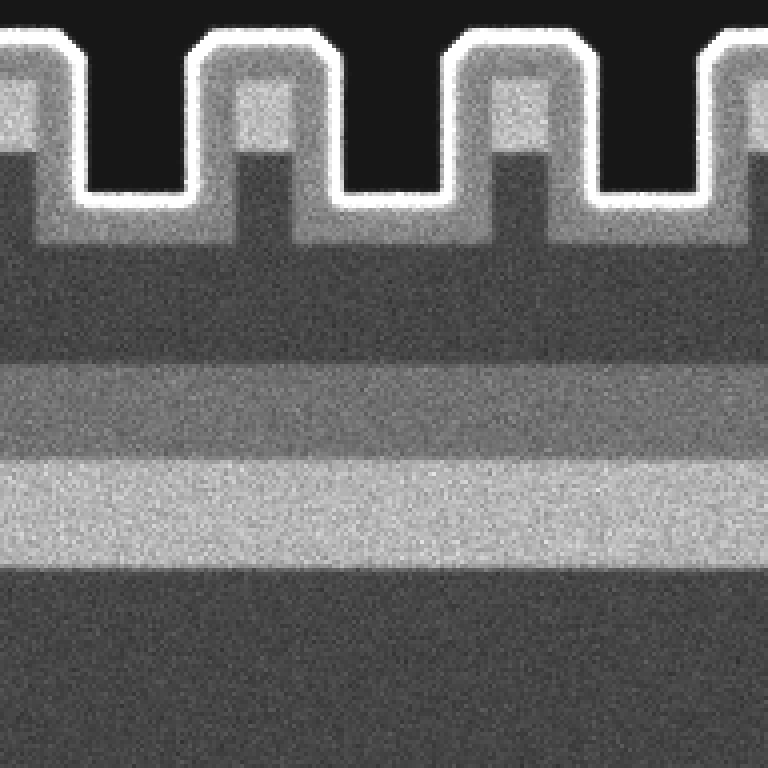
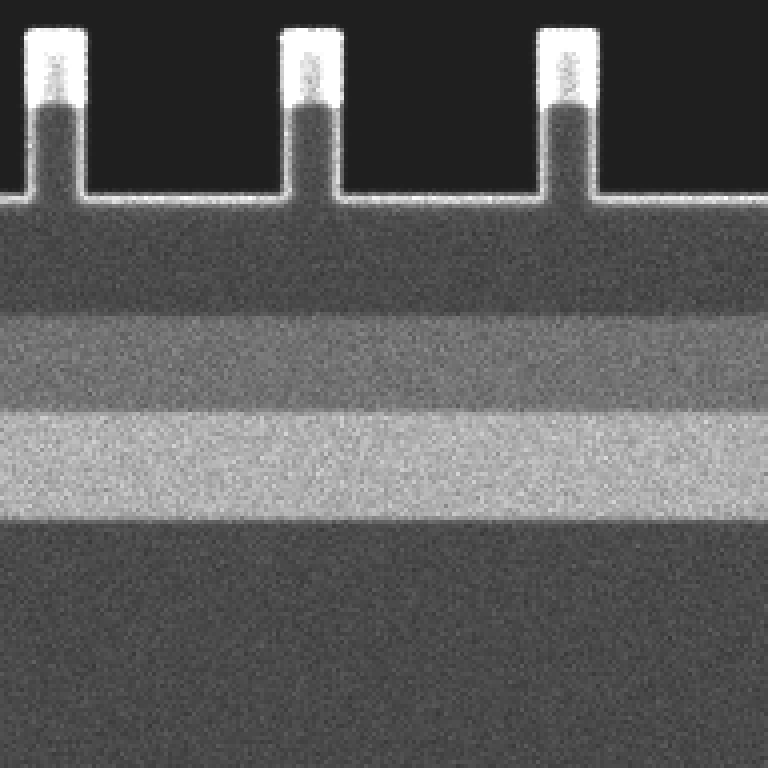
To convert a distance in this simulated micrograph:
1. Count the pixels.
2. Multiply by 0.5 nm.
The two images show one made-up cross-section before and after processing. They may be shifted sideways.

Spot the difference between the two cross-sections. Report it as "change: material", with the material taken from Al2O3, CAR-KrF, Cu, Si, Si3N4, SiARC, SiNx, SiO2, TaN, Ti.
removed: Si3N4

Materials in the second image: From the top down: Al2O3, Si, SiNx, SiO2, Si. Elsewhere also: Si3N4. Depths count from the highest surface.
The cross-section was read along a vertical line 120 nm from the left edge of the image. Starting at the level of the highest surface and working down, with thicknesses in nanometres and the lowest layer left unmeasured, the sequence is empty 82, Si 60, SiNx 48, SiO2 54, Si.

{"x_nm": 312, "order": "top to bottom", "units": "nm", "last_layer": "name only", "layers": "empty 82, Si 60, SiNx 48, SiO2 54, Si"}